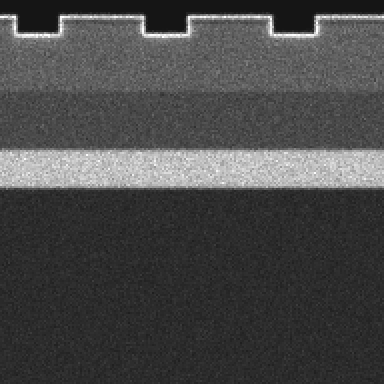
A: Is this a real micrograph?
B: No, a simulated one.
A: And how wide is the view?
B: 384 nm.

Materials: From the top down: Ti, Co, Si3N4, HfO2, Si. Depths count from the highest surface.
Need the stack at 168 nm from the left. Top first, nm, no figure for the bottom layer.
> empty 18, Co 58, Si3N4 58, HfO2 38, Si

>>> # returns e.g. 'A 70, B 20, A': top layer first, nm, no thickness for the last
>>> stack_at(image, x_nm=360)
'Ti 8, Co 68, Si3N4 58, HfO2 38, Si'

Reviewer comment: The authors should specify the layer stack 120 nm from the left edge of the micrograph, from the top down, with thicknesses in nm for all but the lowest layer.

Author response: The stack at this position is Ti 8, Co 68, Si3N4 58, HfO2 38, Si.